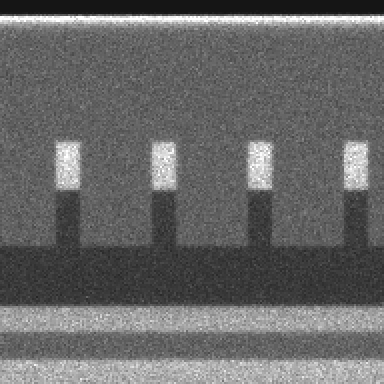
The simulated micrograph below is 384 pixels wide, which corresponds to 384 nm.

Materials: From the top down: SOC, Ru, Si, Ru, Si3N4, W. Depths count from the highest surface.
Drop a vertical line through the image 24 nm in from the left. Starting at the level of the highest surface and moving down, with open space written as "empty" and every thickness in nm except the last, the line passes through SOC 230, Si 60, Ru 26, Si3N4 28, W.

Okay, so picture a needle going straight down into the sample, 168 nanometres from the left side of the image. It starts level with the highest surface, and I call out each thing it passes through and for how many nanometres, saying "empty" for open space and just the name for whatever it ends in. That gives SOC 126, Ru 48, Si 116, Ru 26, Si3N4 28, W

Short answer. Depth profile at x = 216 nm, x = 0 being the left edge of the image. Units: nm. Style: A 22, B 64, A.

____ SOC 230, Si 60, Ru 26, Si3N4 28, W